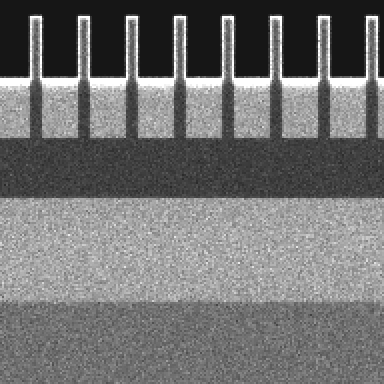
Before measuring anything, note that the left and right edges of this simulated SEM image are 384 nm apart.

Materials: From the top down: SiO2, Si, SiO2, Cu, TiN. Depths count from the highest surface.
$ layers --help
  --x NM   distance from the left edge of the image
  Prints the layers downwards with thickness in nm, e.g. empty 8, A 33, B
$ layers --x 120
empty 62, SiO2 60, Si 60, SiO2 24, Cu 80, TiN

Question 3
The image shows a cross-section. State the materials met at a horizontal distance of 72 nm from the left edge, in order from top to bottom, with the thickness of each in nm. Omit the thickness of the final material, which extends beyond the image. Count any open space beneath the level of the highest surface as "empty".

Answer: empty 62, SiO2 60, Si 60, SiO2 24, Cu 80, TiN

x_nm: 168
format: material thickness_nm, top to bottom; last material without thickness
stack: empty 62, SiO2 60, Si 60, SiO2 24, Cu 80, TiN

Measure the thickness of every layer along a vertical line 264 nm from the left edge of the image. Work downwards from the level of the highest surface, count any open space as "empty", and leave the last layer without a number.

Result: empty 62, SiO2 60, Si 60, SiO2 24, Cu 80, TiN